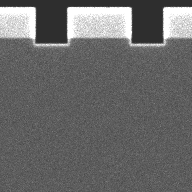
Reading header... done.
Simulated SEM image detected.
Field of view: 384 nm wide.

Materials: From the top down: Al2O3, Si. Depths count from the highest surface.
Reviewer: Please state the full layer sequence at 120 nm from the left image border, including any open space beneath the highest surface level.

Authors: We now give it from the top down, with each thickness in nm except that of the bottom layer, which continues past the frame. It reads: empty 72, Si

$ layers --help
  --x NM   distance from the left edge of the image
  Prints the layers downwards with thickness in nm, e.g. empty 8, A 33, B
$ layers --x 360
Al2O3 60, Si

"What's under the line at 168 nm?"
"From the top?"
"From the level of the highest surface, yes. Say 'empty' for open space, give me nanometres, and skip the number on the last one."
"Al2O3 60, Si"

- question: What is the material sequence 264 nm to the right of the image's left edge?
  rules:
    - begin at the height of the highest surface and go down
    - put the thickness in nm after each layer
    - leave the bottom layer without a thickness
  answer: empty 72, Si